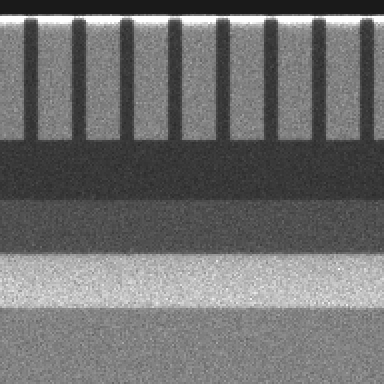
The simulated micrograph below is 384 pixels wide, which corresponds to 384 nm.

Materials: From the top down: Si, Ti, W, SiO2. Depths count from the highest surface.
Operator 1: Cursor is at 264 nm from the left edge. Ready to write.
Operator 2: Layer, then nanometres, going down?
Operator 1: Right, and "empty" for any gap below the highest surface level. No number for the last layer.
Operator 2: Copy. Si 184, Ti 54, W 54, SiO2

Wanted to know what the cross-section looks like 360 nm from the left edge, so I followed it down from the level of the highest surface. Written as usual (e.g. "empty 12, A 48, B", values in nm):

Si 184, Ti 54, W 54, SiO2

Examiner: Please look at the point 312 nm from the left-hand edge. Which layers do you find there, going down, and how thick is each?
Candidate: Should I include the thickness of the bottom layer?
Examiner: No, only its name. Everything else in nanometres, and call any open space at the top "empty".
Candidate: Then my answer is Si 184, Ti 54, W 54, SiO2